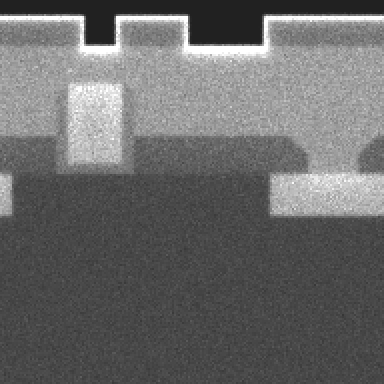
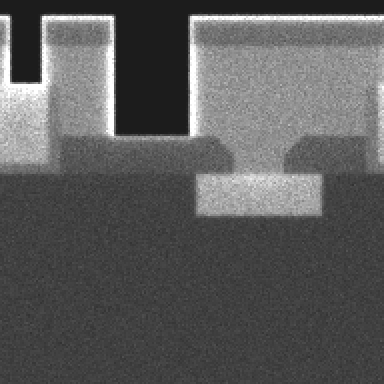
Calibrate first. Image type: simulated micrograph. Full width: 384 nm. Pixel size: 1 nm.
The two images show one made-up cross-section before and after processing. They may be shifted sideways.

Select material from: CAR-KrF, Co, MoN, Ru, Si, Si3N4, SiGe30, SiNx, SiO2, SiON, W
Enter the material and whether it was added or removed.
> SiO2 / removed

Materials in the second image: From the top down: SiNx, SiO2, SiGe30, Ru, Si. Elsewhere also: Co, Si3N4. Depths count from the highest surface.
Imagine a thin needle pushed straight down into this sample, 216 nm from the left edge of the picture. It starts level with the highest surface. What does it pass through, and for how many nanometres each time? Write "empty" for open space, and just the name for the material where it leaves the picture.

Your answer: SiNx 30, SiO2 92, SiGe30 36, Ru 42, Si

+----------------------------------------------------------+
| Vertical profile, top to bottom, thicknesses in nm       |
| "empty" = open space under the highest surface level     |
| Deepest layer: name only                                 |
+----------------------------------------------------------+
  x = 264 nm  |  SiNx 30, SiO2 128, Ru 42, Si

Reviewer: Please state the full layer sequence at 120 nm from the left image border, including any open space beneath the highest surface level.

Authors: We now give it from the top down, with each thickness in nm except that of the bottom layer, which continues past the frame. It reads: empty 120, SiGe30 38, Si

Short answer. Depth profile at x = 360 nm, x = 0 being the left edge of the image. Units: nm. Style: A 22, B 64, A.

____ SiNx 30, SiO2 90, SiGe30 38, Si